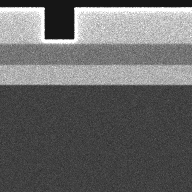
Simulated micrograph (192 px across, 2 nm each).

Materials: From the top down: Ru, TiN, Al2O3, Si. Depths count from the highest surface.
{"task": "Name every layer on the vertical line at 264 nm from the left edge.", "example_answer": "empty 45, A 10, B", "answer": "Ru 72, TiN 42, Al2O3 40, Si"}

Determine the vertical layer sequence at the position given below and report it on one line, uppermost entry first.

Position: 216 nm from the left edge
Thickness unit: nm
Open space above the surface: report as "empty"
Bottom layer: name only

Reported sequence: Ru 72, TiN 42, Al2O3 40, Si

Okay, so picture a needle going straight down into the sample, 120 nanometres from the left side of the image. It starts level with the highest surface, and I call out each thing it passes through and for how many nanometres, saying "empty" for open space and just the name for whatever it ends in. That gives empty 64, Ru 8, TiN 42, Al2O3 40, Si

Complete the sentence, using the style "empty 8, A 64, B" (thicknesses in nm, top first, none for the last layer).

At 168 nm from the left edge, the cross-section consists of Ru 72, TiN 42, Al2O3 40, Si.